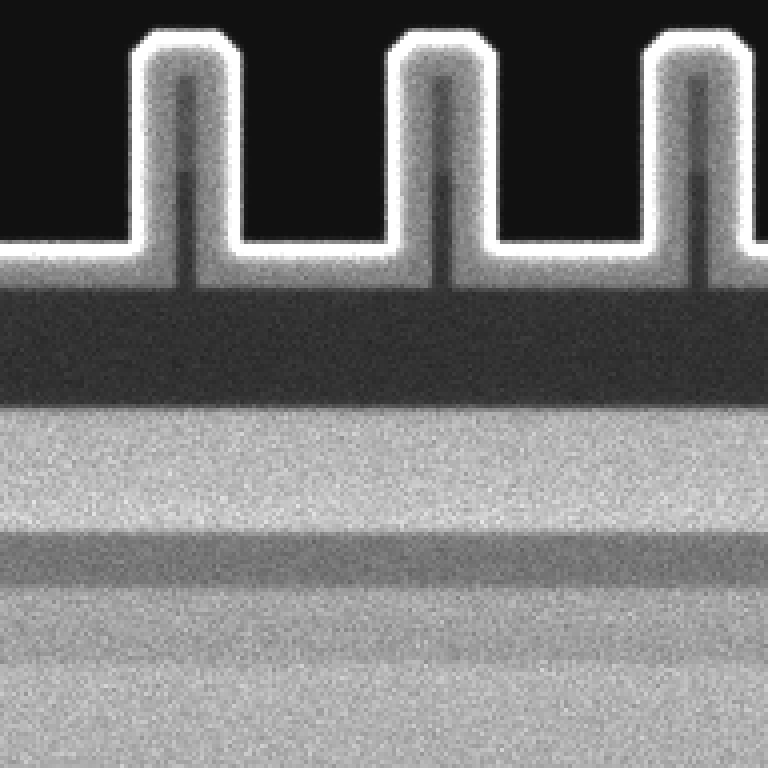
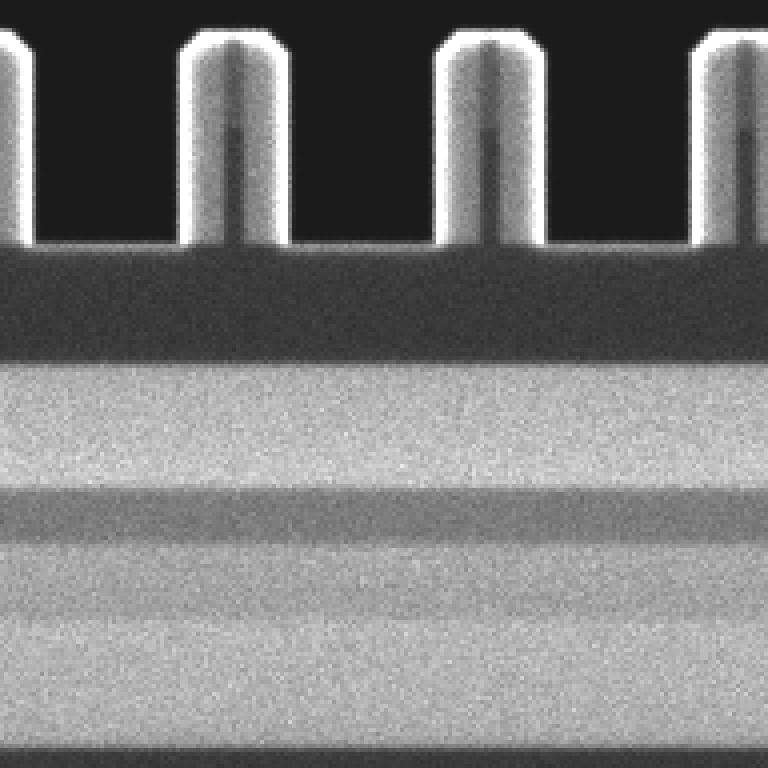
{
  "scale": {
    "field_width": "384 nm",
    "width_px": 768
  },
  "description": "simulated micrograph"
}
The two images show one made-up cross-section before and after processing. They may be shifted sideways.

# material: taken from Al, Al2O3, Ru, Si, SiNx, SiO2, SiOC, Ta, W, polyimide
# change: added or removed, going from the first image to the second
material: Al2O3
change: removed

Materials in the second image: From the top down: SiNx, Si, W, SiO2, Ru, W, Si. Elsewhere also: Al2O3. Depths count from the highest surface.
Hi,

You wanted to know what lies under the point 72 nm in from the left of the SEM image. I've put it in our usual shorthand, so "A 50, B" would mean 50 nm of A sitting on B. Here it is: empty 106, Si 60, W 62, SiO2 28, Ru 38, W 64, Si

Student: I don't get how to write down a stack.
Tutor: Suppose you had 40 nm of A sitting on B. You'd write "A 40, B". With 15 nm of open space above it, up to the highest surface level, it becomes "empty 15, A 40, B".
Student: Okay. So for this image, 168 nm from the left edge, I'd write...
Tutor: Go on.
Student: empty 106, Si 60, W 62, SiO2 28, Ru 38, W 64, Si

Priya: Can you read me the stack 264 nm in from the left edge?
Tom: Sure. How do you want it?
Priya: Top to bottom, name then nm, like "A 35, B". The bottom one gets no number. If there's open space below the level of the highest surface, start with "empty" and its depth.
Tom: empty 4, Al2O3 102, Si 60, W 62, SiO2 28, Ru 38, W 64, Si